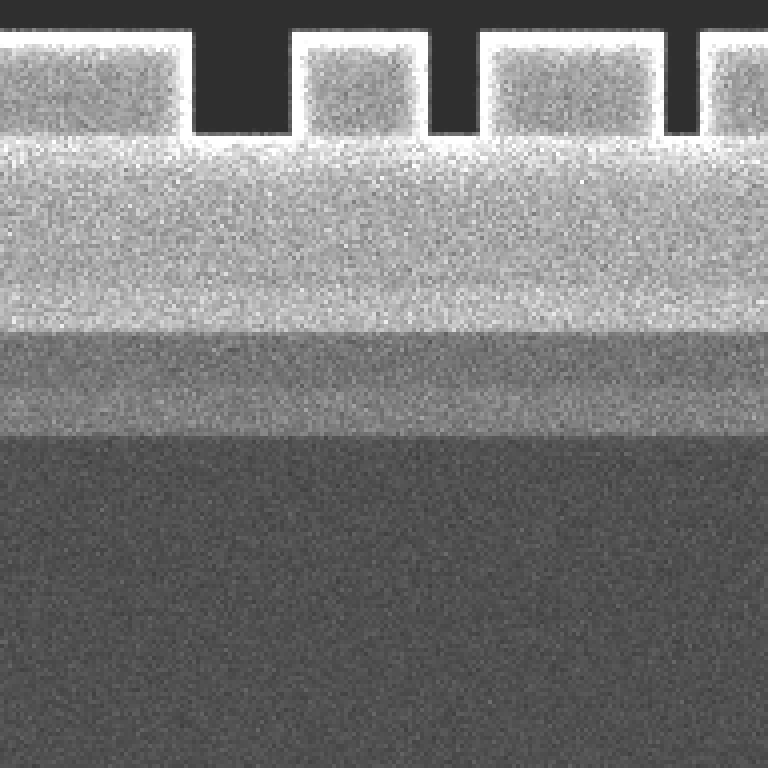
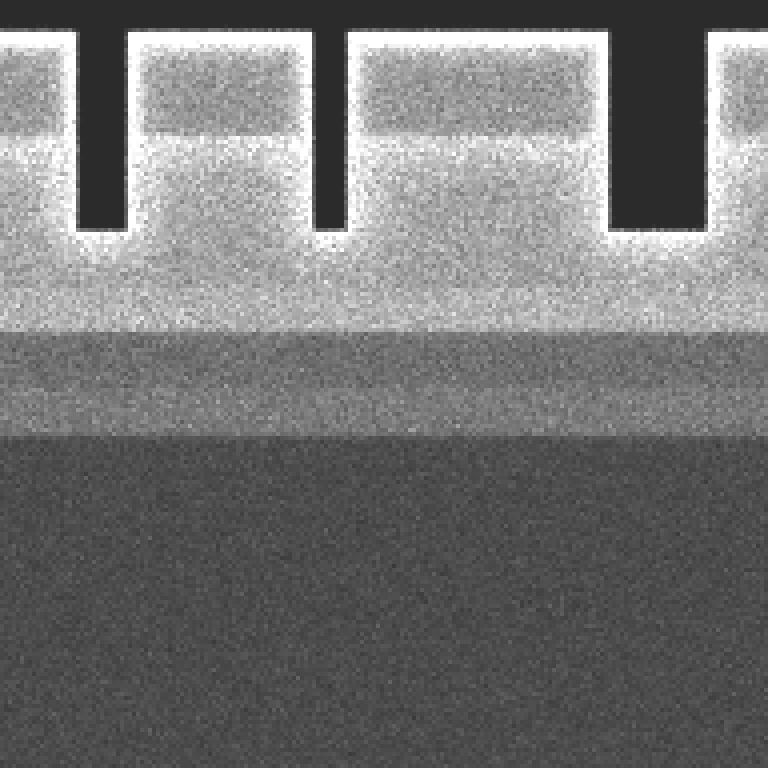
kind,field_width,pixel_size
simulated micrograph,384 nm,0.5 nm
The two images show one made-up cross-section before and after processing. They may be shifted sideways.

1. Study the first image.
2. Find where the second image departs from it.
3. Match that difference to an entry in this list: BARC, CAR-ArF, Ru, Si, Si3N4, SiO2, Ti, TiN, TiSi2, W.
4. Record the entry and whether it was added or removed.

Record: Ru / removed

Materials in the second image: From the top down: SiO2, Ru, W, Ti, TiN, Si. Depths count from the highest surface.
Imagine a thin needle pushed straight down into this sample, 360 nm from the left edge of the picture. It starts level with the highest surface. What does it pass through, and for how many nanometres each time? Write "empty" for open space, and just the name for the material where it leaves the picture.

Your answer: SiO2 52, Ru 76, W 22, Ti 28, TiN 24, Si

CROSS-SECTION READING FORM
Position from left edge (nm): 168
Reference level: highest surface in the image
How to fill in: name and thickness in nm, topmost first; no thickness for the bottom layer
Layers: empty 100, Ru 28, W 22, Ti 28, TiN 24, Si